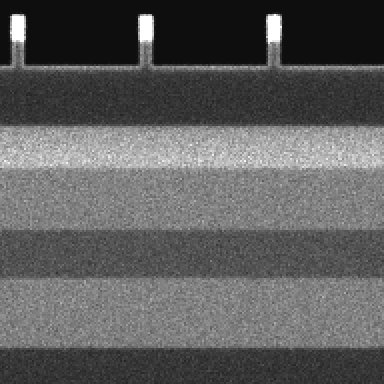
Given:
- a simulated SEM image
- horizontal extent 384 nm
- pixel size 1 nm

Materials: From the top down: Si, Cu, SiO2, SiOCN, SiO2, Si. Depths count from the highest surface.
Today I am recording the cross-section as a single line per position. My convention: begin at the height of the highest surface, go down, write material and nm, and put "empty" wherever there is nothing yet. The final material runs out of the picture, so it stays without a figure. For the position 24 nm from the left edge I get empty 50, Si 60, Cu 42, SiO2 62, SiOCN 48, SiO2 70, Si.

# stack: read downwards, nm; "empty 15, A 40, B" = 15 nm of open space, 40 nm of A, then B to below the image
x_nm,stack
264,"empty 50, Si 60, Cu 42, SiO2 62, SiOCN 48, SiO2 70, Si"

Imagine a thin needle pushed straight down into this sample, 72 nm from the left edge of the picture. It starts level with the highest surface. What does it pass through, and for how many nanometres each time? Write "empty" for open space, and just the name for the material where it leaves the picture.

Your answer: empty 50, Si 60, Cu 42, SiO2 62, SiOCN 48, SiO2 70, Si